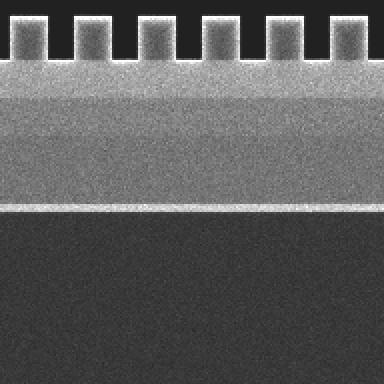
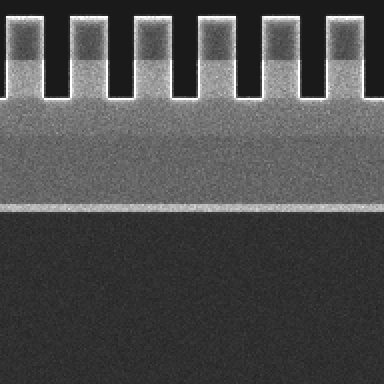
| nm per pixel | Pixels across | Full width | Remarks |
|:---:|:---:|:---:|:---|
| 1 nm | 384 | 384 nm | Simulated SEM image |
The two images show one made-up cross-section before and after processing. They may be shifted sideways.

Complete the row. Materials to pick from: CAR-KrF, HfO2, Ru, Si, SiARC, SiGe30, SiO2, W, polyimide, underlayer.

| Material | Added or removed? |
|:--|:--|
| W | removed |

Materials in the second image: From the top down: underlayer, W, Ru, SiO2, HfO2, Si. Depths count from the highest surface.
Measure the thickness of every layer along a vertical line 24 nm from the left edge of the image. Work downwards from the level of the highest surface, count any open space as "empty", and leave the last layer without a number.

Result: underlayer 44, W 38, Ru 38, SiO2 68, HfO2 8, Si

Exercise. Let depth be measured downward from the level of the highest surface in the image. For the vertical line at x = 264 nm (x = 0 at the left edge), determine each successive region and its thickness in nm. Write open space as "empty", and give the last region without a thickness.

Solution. underlayer 44, W 38, Ru 38, SiO2 68, HfO2 8, Si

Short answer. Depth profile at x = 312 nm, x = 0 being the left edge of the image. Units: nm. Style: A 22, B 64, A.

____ empty 82, Ru 38, SiO2 68, HfO2 8, Si